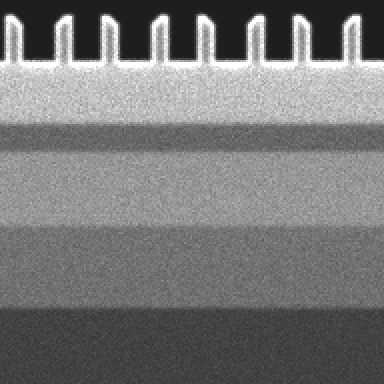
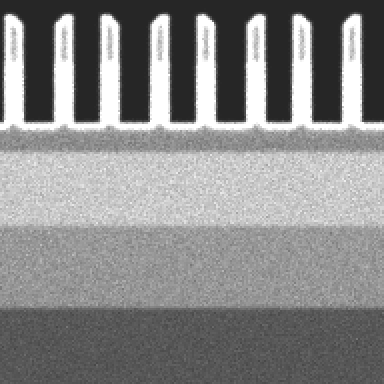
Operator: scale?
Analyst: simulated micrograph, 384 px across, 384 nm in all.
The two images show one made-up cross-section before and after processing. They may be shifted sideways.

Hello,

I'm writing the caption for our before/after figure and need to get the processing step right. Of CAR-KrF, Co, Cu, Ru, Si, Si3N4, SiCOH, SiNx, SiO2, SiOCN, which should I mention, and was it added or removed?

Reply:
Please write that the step removed Co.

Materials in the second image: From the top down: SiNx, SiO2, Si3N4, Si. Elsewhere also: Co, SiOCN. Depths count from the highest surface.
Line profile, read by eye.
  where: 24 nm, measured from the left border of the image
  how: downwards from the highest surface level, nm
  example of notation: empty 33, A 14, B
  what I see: empty 108, SiNx 28, SiO2 74, Si3N4 82, Si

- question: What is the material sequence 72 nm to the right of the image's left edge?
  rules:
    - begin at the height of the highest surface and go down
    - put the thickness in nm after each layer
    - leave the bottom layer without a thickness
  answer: empty 108, SiNx 28, SiO2 74, Si3N4 82, Si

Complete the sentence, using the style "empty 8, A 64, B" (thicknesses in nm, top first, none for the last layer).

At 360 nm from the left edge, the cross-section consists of empty 108, SiNx 28, SiO2 74, Si3N4 82, Si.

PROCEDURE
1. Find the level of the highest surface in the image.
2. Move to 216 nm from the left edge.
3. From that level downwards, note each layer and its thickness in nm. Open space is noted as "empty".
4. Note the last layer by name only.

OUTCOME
empty 108, SiNx 28, SiO2 74, Si3N4 82, Si